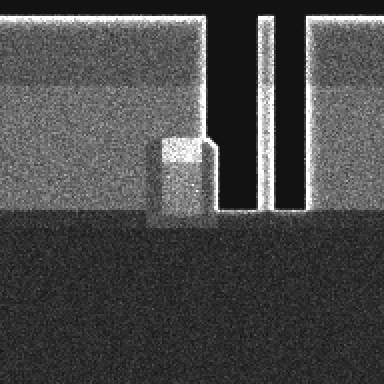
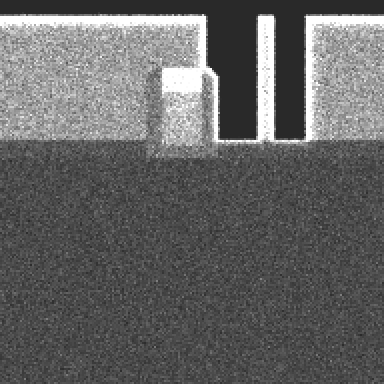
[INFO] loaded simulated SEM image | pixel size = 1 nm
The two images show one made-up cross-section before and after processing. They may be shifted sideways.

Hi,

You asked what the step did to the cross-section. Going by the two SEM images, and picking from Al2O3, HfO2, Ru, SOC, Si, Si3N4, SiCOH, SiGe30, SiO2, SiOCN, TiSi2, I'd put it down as SOC, removed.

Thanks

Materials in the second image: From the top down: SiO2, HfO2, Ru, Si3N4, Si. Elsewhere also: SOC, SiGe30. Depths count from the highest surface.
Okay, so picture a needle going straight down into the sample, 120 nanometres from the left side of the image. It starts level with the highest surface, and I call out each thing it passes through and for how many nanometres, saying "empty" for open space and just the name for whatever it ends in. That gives SiO2 124, SiGe30 18, Si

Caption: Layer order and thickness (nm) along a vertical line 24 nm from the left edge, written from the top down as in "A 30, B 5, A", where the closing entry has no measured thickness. SiO2 124, SiGe30 18, Si